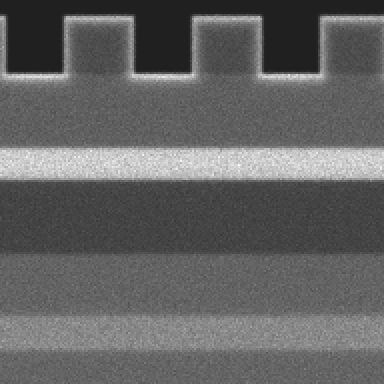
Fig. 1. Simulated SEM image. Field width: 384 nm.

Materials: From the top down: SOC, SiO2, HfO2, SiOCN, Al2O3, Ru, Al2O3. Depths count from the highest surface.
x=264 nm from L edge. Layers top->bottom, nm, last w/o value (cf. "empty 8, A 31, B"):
empty 58, SiO2 74, HfO2 32, SiOCN 74, Al2O3 62, Ru 34, Al2O3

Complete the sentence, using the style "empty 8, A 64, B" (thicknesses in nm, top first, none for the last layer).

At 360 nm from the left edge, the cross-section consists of SOC 58, SiO2 74, HfO2 32, SiOCN 74, Al2O3 62, Ru 34, Al2O3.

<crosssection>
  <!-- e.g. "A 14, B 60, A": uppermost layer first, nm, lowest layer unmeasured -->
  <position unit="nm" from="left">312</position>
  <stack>empty 58, SiO2 74, HfO2 32, SiOCN 74, Al2O3 62, Ru 34, Al2O3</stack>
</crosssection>